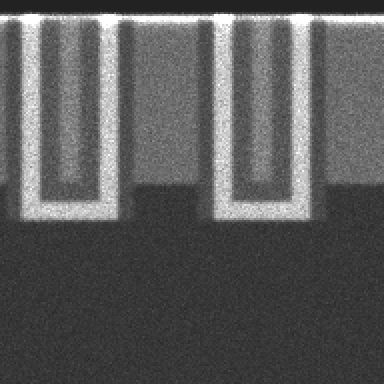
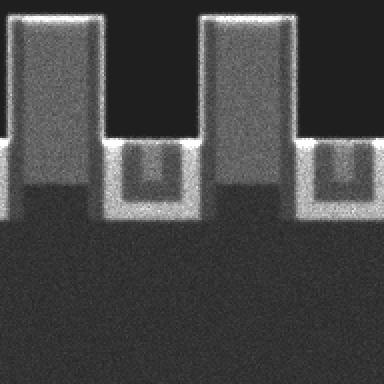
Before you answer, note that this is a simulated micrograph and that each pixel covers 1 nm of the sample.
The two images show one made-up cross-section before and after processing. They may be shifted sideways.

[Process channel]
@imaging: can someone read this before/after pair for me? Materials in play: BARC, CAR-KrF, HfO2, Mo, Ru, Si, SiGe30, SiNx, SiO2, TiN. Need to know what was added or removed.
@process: HfO2 and Ru and TiN removed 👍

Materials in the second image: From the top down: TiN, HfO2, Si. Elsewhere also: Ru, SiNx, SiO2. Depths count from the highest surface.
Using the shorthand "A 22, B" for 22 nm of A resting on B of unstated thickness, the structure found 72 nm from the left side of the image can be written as SiO2 168, Si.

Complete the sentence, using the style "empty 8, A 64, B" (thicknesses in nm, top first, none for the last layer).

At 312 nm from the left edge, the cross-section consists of empty 124, HfO2 80, Si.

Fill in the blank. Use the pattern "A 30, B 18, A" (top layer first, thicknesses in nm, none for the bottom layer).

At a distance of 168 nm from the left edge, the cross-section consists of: empty 124, TiN 62, HfO2 18, Si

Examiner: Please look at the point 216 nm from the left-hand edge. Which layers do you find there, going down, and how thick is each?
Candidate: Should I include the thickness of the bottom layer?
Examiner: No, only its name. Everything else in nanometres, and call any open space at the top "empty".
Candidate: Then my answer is SiO2 168, Si